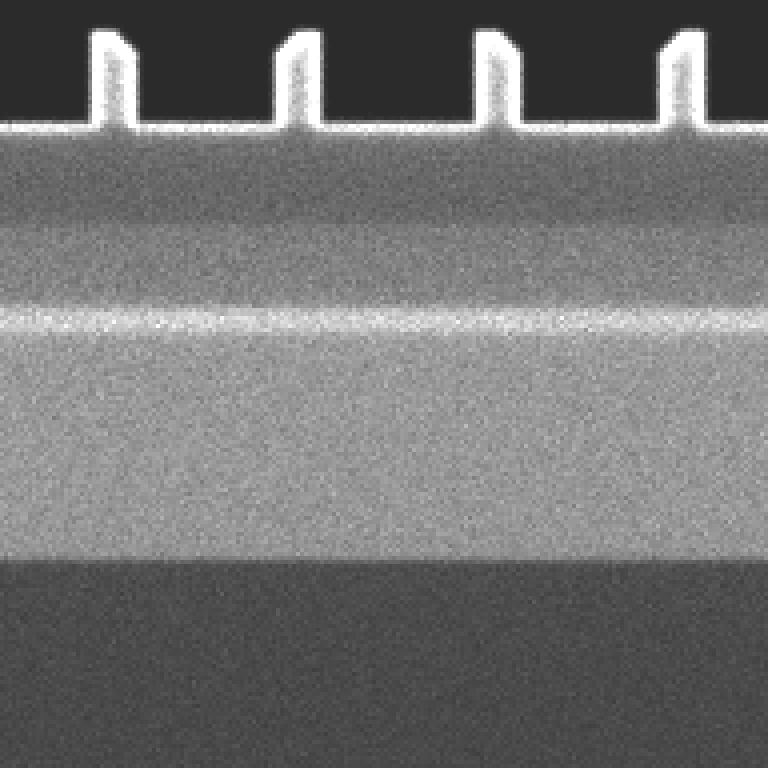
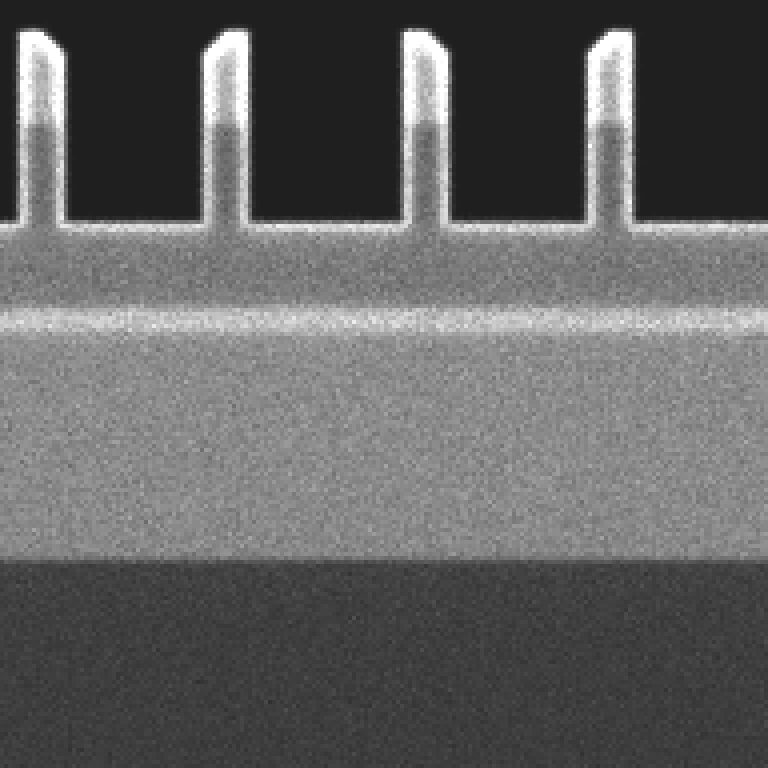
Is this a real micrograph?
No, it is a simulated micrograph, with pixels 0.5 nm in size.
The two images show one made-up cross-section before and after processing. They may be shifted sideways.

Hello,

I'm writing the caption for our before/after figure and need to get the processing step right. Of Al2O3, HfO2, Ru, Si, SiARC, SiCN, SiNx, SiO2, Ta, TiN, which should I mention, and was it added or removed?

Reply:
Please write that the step removed SiNx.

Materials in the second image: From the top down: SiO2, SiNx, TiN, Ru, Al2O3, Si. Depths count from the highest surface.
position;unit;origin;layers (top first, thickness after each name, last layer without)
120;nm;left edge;SiO2 46, SiNx 50, TiN 42, Ru 12, Al2O3 114, Si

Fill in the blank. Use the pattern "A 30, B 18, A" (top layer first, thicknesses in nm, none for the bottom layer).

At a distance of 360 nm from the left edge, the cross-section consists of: empty 96, TiN 42, Ru 12, Al2O3 114, Si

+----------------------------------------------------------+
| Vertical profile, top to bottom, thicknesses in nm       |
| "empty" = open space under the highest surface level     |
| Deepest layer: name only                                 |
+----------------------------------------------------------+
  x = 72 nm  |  empty 96, TiN 42, Ru 12, Al2O3 114, Si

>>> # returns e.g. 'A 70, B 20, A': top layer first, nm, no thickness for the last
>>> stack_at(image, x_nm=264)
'empty 96, TiN 42, Ru 12, Al2O3 114, Si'